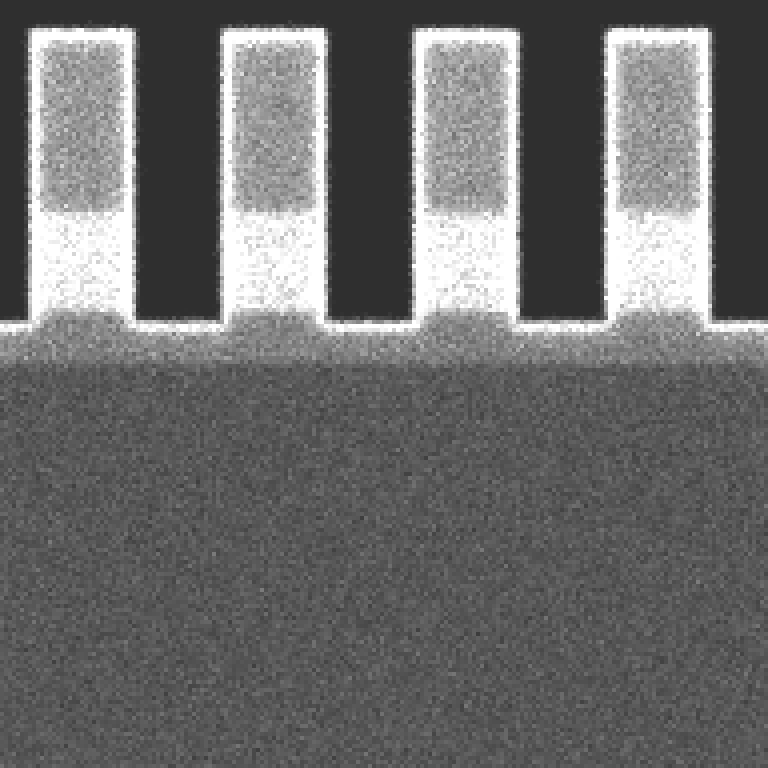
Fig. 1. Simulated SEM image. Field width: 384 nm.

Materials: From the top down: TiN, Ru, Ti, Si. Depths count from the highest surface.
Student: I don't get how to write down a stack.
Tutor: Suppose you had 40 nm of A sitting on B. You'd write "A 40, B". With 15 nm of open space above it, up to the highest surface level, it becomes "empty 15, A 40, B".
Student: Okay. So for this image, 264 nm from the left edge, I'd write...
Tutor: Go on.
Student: empty 146, Ti 20, Si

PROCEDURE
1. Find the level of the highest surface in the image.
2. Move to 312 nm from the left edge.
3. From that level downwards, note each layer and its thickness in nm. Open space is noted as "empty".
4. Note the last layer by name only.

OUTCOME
TiN 90, Ru 50, Ti 26, Si